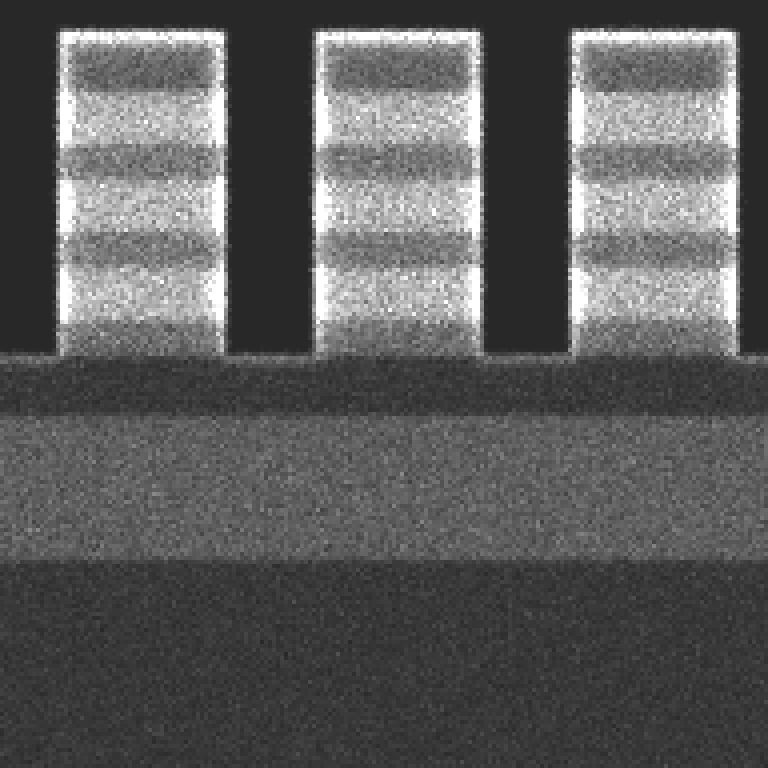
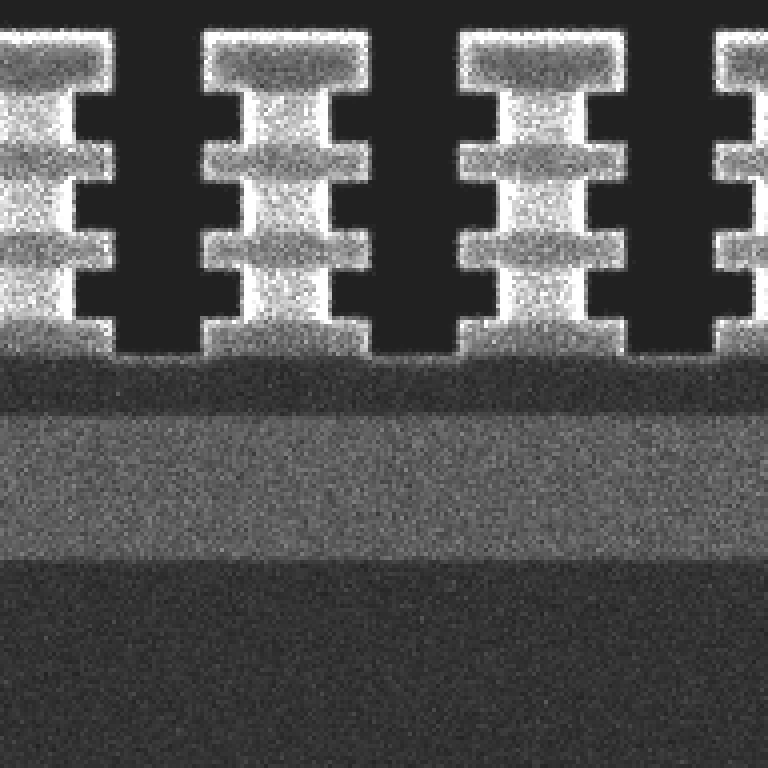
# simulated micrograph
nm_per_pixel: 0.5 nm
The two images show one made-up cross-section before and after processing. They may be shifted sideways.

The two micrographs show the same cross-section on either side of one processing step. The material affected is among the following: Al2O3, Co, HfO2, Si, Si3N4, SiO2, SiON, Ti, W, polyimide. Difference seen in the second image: HfO2 removed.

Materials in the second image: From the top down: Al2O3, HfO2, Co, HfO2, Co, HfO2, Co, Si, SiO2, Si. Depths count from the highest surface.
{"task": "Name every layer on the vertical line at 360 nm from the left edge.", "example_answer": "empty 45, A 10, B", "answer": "Al2O3 30, empty 26, Co 18, empty 26, Co 18, empty 26, Co 18, Si 30, SiO2 72, Si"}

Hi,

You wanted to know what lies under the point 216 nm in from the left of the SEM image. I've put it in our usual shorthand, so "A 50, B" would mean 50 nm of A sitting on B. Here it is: empty 162, Si 30, SiO2 72, Si